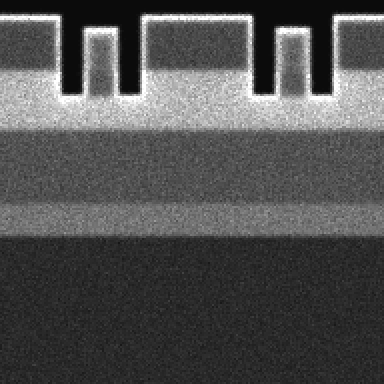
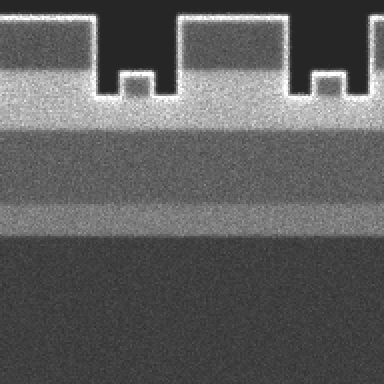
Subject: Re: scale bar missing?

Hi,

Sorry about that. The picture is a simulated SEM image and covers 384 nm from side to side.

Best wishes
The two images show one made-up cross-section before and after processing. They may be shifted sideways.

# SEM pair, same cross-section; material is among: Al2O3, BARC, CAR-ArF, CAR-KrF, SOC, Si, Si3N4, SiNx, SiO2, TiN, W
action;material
removed;SOC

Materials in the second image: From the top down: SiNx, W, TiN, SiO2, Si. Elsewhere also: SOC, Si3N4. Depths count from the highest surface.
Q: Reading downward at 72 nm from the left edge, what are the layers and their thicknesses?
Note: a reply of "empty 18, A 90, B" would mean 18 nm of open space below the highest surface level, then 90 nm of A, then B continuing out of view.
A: SiNx 54, W 60, TiN 74, SiO2 32, Si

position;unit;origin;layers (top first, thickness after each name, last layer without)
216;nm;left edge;SiNx 54, W 60, TiN 74, SiO2 32, Si